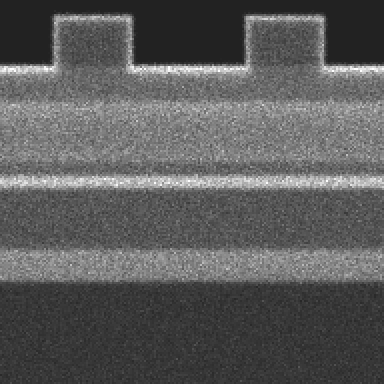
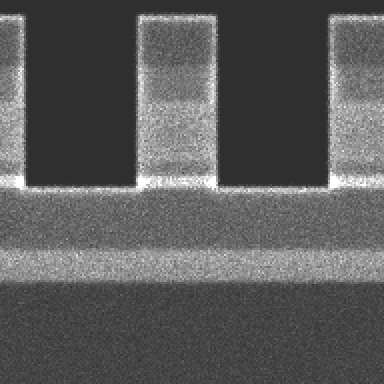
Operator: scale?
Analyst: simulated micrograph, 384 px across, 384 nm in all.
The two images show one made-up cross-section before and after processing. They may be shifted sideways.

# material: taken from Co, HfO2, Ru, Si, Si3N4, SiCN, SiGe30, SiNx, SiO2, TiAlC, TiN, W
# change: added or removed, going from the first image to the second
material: HfO2 and Ru and SiO2 and TiN
change: removed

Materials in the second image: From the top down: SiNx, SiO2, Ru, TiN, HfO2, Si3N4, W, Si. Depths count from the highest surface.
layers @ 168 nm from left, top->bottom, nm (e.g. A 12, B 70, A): SiNx 50, SiO2 36, Ru 60, TiN 14, HfO2 12, Si3N4 62, W 32, Si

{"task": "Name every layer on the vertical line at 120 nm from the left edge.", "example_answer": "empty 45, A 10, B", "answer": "empty 172, Si3N4 62, W 32, Si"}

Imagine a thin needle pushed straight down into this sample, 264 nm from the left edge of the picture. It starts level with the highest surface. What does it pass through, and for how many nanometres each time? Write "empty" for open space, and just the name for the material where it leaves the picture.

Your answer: empty 172, Si3N4 62, W 32, Si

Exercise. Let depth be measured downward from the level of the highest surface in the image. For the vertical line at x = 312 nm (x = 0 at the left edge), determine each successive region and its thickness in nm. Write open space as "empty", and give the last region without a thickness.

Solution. empty 172, Si3N4 62, W 32, Si